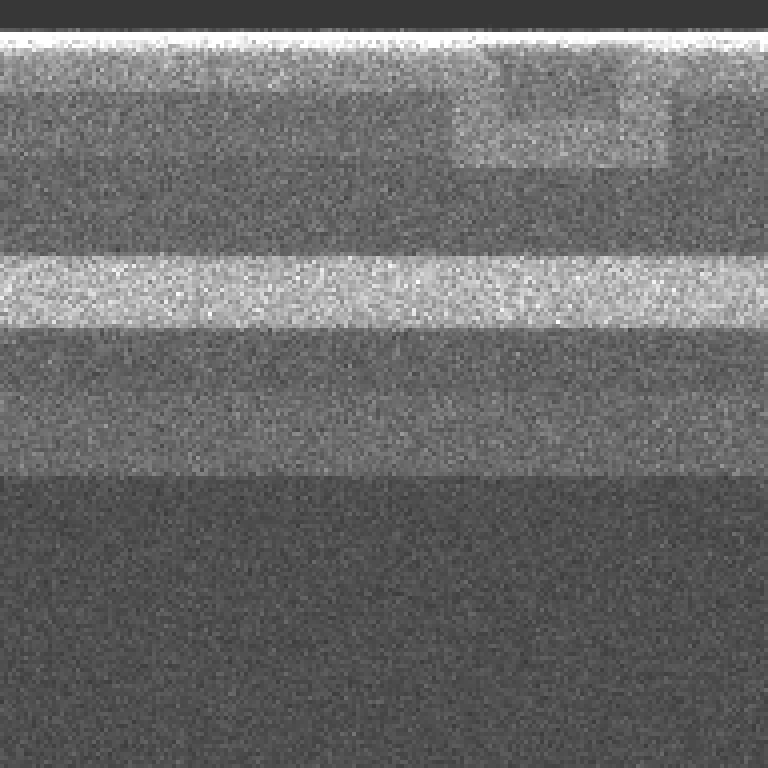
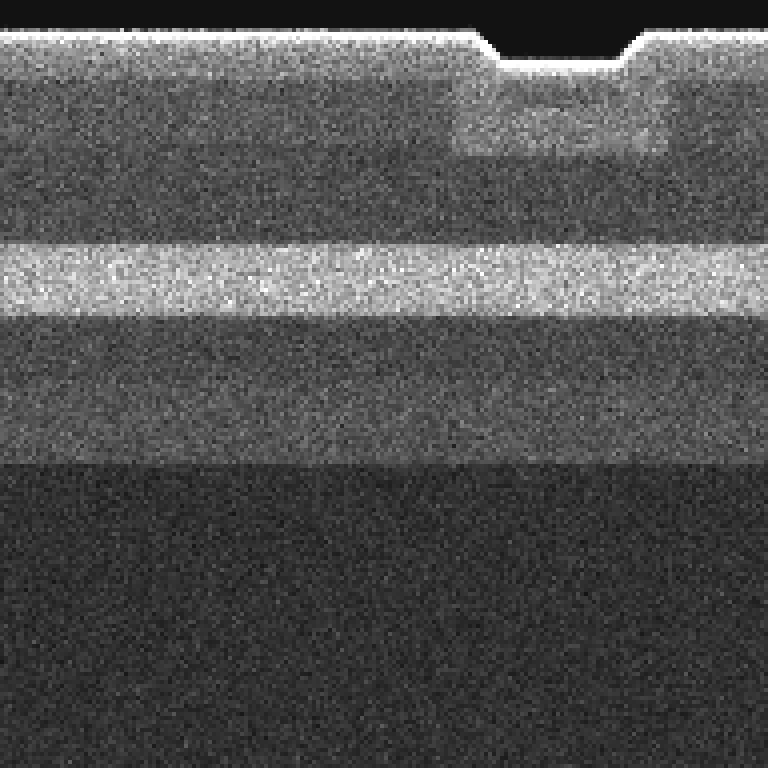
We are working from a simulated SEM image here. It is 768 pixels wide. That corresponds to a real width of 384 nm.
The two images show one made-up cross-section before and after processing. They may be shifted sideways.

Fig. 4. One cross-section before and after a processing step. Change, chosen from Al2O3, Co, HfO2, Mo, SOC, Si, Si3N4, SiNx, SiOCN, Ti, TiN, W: SOC removed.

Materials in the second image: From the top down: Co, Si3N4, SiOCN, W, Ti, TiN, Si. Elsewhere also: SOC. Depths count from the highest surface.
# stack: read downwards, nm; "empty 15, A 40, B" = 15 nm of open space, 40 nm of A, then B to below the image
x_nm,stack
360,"Co 24, Si3N4 32, SiOCN 50, W 36, Ti 32, TiN 42, Si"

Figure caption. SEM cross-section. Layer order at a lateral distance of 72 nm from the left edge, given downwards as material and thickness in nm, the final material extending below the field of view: Co 24, Si3N4 32, SiOCN 50, W 36, Ti 32, TiN 42, Si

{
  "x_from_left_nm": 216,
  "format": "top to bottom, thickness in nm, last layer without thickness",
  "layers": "Co 24, Si3N4 32, SiOCN 50, W 36, Ti 32, TiN 42, Si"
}